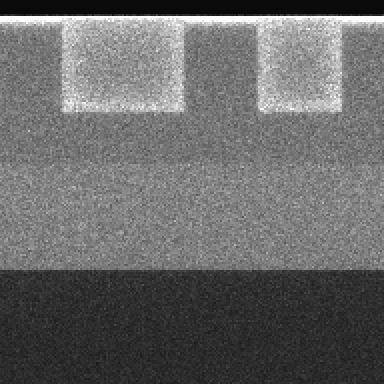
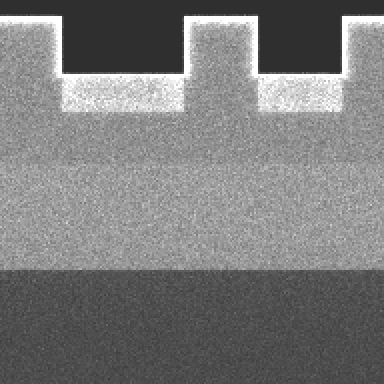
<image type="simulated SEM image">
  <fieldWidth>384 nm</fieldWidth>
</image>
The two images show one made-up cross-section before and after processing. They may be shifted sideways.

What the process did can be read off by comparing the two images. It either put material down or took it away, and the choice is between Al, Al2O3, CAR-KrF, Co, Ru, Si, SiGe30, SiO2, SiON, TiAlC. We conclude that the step removed Co and Ru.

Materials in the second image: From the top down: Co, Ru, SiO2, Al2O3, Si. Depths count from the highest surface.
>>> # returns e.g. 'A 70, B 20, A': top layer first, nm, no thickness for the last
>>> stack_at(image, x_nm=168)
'empty 58, Co 24, Ru 14, SiO2 52, Al2O3 106, Si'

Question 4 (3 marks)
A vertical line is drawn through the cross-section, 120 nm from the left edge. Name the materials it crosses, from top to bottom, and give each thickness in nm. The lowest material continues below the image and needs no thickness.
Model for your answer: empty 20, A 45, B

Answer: empty 58, Co 24, Ru 14, SiO2 52, Al2O3 106, Si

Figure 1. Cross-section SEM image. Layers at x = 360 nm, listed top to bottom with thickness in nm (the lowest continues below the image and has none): SiO2 148, Al2O3 106, Si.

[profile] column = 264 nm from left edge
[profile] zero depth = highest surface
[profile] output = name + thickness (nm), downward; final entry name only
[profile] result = empty 58, Ru 38, SiO2 52, Al2O3 106, Si